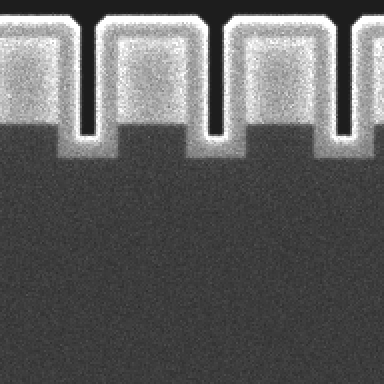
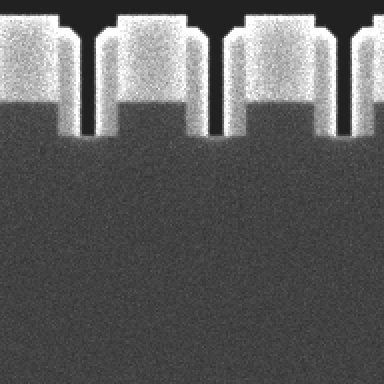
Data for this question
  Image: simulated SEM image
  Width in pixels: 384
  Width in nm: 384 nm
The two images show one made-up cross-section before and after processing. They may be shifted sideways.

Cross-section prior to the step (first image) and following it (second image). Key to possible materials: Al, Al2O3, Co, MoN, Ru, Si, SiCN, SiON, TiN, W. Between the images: Al2O3 was removed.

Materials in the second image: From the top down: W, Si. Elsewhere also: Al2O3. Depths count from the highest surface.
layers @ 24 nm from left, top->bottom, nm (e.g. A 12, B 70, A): W 86, Si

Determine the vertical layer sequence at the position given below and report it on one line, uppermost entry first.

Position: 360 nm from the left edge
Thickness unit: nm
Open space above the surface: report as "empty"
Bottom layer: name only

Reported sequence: empty 14, Al2O3 106, Si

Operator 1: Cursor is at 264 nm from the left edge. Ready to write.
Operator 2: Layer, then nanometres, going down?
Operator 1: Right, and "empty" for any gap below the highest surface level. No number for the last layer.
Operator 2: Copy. W 86, Si